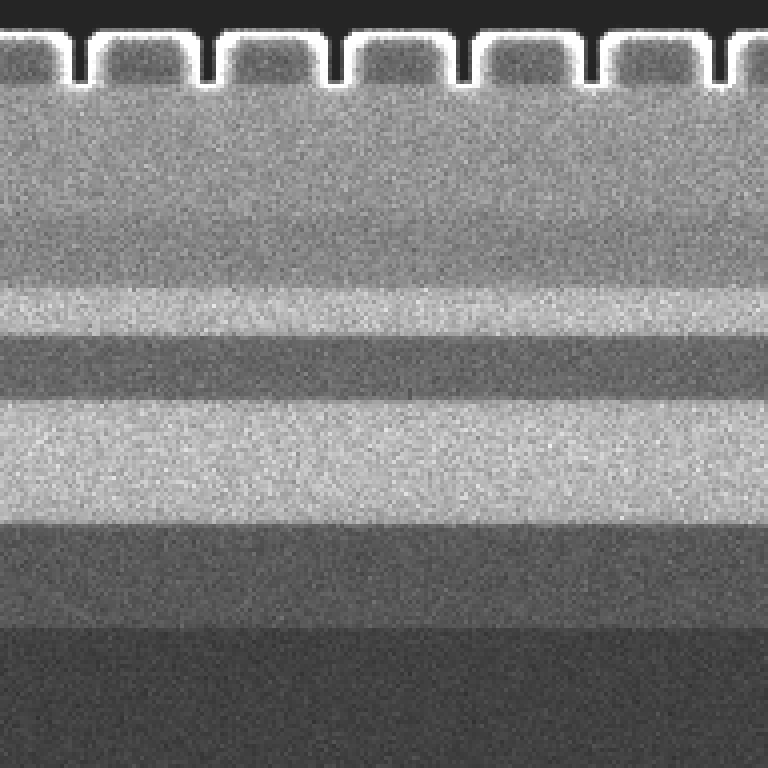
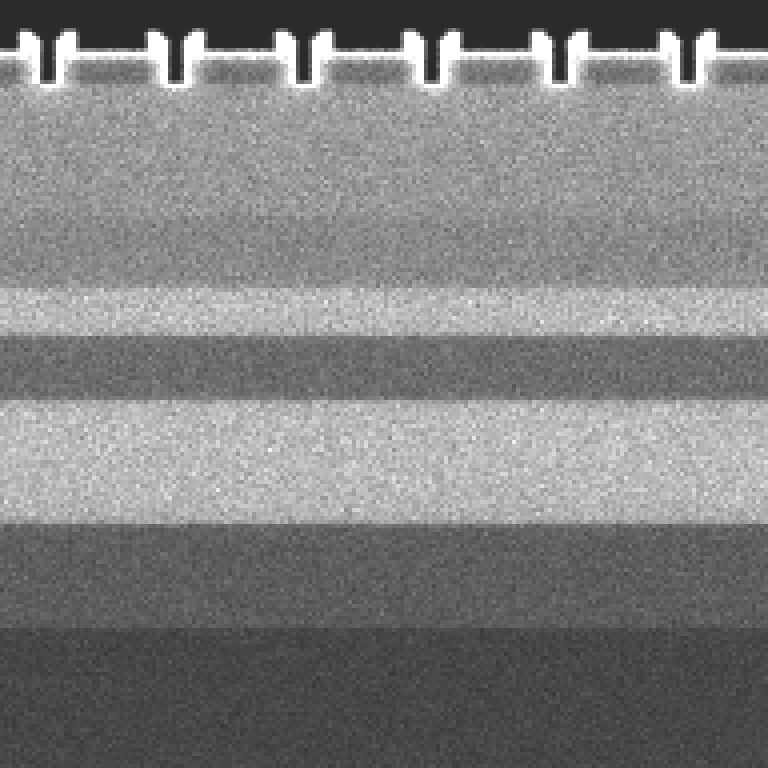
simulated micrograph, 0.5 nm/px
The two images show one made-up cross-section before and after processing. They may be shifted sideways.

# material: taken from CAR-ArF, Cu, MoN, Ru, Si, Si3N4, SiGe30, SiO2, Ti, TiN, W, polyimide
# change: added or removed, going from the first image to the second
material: TiN
change: removed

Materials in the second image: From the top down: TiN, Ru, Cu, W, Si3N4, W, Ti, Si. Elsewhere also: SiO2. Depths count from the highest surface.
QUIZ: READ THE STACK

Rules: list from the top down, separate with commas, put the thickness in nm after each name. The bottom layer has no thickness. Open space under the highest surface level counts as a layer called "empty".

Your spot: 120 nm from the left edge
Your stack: empty 10, TiN 16, Ru 66, Cu 36, W 24, Si3N4 32, W 62, Ti 52, Si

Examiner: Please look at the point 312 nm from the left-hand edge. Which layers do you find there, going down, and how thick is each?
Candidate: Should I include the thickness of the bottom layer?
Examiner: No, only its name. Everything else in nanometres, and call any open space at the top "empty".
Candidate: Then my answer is empty 10, TiN 16, Ru 66, Cu 36, W 24, Si3N4 32, W 62, Ti 52, Si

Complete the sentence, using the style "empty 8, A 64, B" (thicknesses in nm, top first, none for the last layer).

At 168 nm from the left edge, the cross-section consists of empty 10, TiN 16, Ru 66, Cu 36, W 24, Si3N4 32, W 62, Ti 52, Si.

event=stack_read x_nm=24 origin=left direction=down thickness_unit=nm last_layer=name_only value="empty 26, Ru 66, Cu 36, W 24, Si3N4 32, W 62, Ti 52, Si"